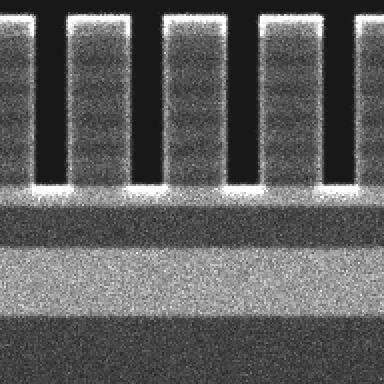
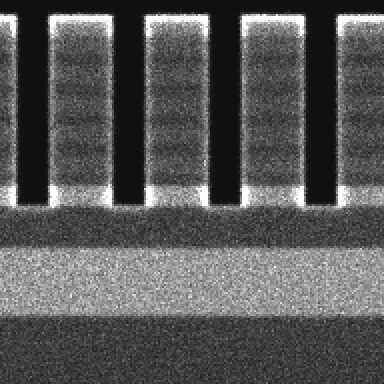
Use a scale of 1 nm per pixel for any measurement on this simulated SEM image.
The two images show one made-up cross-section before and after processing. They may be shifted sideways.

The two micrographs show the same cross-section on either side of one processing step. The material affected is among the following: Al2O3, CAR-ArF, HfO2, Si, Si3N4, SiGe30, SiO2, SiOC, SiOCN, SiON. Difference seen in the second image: SiO2 removed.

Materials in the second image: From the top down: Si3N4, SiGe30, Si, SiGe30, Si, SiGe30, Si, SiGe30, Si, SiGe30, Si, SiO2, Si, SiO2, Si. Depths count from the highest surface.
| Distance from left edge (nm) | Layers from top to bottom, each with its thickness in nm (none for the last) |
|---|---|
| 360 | Si3N4 20, SiGe30 18, Si 12, SiGe30 18, Si 12, SiGe30 18, Si 12, SiGe30 18, Si 12, SiGe30 18, Si 12, SiO2 20, Si 42, SiO2 68, Si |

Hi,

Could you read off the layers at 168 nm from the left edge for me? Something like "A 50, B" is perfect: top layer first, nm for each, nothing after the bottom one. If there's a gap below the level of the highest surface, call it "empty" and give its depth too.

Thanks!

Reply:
Si3N4 20, SiGe30 18, Si 12, SiGe30 18, Si 12, SiGe30 18, Si 12, SiGe30 18, Si 12, SiGe30 18, Si 12, SiO2 20, Si 42, SiO2 68, Si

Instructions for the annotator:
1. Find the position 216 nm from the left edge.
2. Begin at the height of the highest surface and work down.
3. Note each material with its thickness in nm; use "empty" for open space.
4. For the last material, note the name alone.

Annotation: empty 190, Si 42, SiO2 68, Si